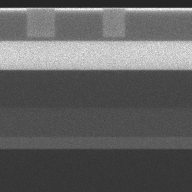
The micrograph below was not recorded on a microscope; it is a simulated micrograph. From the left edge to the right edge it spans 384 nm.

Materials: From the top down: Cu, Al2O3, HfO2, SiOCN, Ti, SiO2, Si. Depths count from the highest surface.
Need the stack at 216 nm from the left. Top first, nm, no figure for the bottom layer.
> Cu 58, Al2O3 8, HfO2 58, SiOCN 76, Ti 58, SiO2 24, Si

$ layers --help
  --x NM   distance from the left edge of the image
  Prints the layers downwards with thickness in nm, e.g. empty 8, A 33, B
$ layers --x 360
Al2O3 66, HfO2 58, SiOCN 76, Ti 58, SiO2 24, Si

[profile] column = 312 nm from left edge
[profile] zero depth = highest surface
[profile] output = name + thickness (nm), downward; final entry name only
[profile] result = Al2O3 66, HfO2 58, SiOCN 76, Ti 58, SiO2 24, Si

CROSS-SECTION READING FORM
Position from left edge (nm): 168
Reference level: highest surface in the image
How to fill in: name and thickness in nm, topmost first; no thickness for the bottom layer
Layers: Al2O3 66, HfO2 58, SiOCN 76, Ti 58, SiO2 24, Si